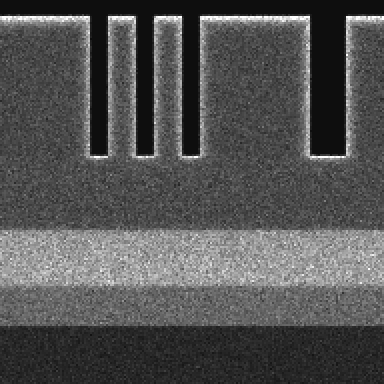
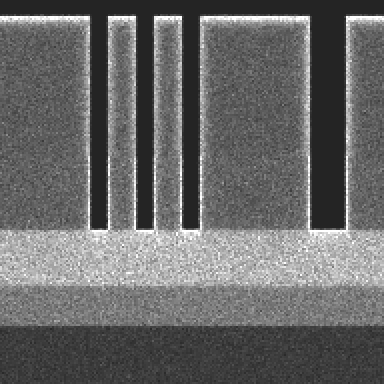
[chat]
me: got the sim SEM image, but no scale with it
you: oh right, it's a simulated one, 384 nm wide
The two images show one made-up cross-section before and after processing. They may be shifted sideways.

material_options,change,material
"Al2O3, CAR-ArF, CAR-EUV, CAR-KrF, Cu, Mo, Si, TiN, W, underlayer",removed,TiN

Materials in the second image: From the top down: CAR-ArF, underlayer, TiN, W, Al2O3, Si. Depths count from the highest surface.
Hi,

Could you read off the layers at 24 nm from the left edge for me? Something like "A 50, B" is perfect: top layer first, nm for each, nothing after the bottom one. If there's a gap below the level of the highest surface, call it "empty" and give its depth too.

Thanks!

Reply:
CAR-ArF 80, underlayer 60, TiN 74, W 56, Al2O3 40, Si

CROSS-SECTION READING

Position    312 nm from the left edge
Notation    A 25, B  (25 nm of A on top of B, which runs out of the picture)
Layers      empty 214, W 56, Al2O3 40, Si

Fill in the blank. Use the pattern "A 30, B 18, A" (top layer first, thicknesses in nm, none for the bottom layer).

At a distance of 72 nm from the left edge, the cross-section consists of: CAR-ArF 80, underlayer 60, TiN 74, W 56, Al2O3 40, Si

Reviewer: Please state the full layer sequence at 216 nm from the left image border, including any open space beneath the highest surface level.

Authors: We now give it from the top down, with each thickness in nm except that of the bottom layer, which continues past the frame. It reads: CAR-ArF 80, underlayer 60, TiN 74, W 56, Al2O3 40, Si